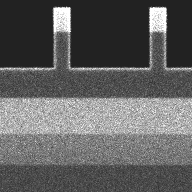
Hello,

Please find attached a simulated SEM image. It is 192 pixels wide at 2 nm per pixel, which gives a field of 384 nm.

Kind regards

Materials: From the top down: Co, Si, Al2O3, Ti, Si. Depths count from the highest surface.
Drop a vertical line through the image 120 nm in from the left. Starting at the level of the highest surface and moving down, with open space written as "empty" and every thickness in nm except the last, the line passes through Co 48, Si 132, Al2O3 72, Ti 62, Si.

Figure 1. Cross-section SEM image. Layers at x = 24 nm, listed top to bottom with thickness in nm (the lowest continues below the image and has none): empty 120, Si 60, Al2O3 72, Ti 62, Si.